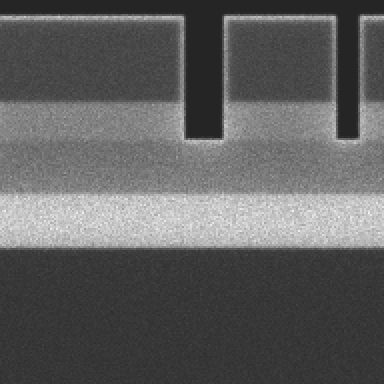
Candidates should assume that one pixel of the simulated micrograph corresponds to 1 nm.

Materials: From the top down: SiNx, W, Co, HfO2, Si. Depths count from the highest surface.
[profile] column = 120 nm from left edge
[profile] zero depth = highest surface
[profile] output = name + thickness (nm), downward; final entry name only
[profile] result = SiNx 86, W 38, Co 54, HfO2 54, Si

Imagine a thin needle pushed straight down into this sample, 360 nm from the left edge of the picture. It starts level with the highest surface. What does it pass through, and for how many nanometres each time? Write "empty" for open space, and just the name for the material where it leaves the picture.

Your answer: SiNx 86, W 38, Co 54, HfO2 54, Si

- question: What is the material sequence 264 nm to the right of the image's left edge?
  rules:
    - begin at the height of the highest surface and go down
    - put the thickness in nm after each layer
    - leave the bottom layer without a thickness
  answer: SiNx 86, W 38, Co 54, HfO2 54, Si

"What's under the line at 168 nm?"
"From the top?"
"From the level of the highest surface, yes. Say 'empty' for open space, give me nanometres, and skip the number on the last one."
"SiNx 86, W 38, Co 54, HfO2 54, Si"